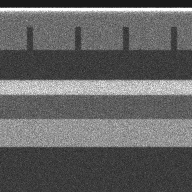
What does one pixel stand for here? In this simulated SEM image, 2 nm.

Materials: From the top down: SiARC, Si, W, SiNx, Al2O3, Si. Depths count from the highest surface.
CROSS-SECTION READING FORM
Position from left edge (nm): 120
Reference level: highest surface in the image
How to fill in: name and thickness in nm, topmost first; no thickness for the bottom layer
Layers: SiARC 84, Si 60, W 30, SiNx 48, Al2O3 56, Si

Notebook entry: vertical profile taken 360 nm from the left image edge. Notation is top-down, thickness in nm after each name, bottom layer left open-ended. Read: SiARC 84, Si 60, W 30, SiNx 48, Al2O3 56, Si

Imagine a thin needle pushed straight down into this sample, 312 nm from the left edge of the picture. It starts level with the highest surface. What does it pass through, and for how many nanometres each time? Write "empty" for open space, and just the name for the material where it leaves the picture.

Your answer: SiARC 84, Si 60, W 30, SiNx 48, Al2O3 56, Si